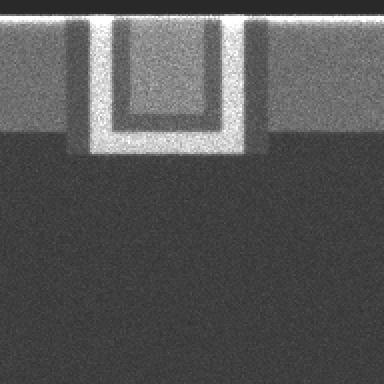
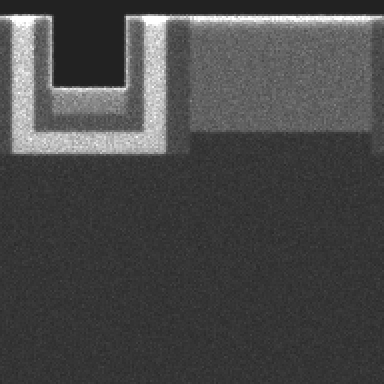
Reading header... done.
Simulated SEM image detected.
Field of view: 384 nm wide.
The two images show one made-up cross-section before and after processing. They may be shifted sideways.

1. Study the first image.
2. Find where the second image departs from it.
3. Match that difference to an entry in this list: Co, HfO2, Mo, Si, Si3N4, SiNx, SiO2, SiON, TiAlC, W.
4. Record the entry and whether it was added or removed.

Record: Co / removed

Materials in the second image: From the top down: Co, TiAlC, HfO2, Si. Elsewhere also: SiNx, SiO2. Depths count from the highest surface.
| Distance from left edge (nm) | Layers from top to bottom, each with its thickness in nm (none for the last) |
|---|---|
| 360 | SiO2 116, Si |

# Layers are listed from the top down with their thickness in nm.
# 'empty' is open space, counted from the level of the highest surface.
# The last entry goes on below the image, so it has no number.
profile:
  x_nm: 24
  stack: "HfO2 138, Si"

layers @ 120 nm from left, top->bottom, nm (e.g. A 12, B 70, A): empty 72, Co 26, TiAlC 18, HfO2 22, Si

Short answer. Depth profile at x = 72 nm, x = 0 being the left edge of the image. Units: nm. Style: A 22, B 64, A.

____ empty 72, Co 26, TiAlC 18, HfO2 22, Si